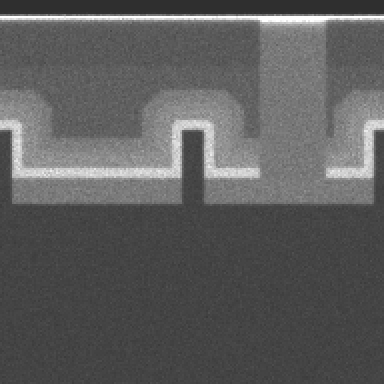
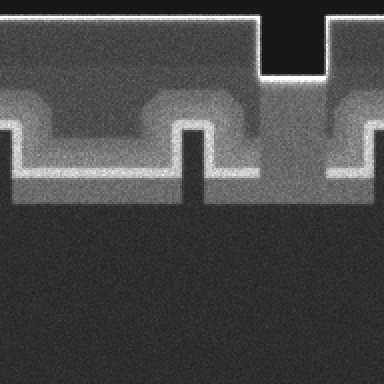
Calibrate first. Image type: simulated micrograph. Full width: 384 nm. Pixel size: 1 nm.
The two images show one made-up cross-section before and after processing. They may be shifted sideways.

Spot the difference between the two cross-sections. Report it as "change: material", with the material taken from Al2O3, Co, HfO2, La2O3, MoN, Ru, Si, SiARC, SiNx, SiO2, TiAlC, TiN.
removed: SiO2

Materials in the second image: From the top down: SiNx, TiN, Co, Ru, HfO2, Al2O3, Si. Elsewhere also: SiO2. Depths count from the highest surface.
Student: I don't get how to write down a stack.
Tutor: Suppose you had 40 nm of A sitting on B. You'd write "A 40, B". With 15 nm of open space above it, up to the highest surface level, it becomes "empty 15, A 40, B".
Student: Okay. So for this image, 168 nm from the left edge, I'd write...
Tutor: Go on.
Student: SiNx 50, TiN 24, Co 14, Ru 64, HfO2 10, Al2O3 26, Si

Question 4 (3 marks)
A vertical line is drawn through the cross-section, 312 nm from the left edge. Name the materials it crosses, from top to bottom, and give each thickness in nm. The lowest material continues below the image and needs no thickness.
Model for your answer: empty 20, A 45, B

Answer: empty 60, SiO2 102, Al2O3 26, Si